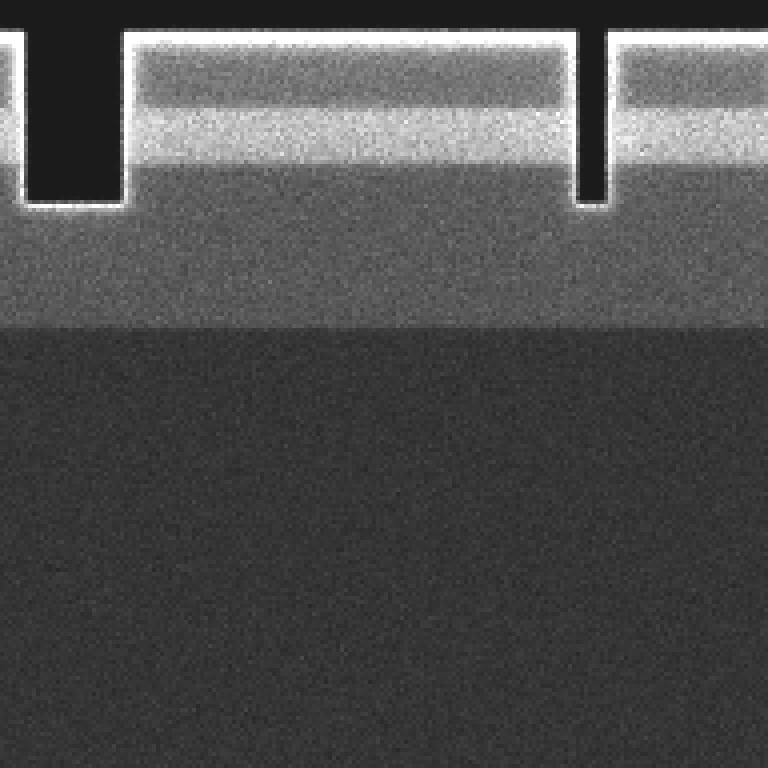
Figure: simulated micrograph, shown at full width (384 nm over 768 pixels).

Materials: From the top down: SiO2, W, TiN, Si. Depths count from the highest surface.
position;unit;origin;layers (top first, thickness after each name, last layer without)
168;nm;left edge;SiO2 38, W 28, TiN 82, Si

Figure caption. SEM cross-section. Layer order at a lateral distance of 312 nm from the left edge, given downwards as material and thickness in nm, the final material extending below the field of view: SiO2 38, W 28, TiN 82, Si